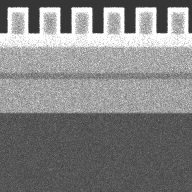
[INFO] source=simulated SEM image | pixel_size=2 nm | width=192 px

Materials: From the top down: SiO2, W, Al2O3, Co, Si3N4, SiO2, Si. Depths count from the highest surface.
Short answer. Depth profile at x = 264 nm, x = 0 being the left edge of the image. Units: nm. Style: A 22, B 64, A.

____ empty 52, W 26, Al2O3 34, Co 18, Si3N4 12, SiO2 68, Si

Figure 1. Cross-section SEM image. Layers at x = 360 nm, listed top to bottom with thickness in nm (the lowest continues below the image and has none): SiO2 52, W 26, Al2O3 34, Co 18, Si3N4 12, SiO2 68, Si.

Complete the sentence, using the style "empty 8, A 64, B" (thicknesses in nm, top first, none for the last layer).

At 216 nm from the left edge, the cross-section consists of SiO2 52, W 26, Al2O3 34, Co 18, Si3N4 12, SiO2 68, Si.